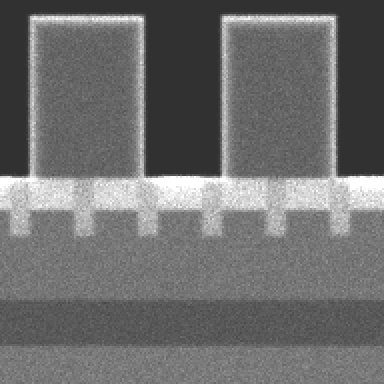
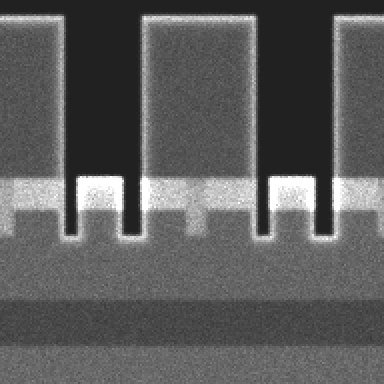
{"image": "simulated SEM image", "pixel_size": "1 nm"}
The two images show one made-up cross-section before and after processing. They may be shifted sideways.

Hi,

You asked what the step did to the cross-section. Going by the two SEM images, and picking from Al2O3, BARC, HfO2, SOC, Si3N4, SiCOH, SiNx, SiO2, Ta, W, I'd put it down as W, removed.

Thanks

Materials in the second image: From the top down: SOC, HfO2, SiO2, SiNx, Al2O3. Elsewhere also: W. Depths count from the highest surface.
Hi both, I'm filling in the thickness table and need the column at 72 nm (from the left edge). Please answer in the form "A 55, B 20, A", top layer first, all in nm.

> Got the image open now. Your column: empty 220, SiO2 64, SiNx 46, Al2O3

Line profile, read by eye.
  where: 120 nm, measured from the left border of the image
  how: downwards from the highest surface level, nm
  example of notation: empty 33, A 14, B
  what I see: empty 162, HfO2 32, SiO2 90, SiNx 46, Al2O3